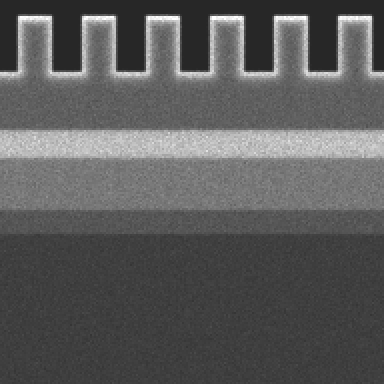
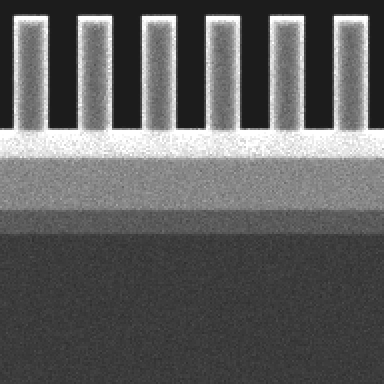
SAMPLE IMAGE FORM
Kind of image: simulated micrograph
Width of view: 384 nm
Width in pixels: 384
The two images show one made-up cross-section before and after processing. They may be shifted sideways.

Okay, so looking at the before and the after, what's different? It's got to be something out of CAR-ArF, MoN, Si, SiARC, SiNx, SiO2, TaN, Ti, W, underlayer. underlayer, removed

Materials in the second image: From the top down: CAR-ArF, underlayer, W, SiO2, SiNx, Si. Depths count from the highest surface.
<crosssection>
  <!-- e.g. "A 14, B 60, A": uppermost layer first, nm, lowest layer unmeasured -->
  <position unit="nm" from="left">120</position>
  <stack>empty 114, W 28, SiO2 52, SiNx 24, Si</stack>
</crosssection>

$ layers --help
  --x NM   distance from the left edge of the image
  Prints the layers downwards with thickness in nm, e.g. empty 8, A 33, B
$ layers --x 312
empty 114, W 28, SiO2 52, SiNx 24, Si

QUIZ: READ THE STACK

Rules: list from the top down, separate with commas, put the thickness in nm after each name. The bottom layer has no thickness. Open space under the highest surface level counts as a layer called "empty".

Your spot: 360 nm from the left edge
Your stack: CAR-ArF 56, underlayer 58, W 28, SiO2 52, SiNx 24, Si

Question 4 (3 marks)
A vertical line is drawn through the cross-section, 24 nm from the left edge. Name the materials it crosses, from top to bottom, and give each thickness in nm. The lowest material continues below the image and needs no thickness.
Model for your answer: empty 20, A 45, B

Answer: CAR-ArF 56, underlayer 58, W 28, SiO2 52, SiNx 24, Si